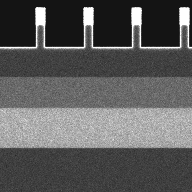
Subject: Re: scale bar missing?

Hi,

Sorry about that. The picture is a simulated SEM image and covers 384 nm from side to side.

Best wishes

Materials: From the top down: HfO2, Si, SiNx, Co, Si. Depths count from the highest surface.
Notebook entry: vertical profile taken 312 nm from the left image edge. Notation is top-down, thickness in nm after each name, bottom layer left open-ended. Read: empty 78, Si 60, SiNx 62, Co 80, Si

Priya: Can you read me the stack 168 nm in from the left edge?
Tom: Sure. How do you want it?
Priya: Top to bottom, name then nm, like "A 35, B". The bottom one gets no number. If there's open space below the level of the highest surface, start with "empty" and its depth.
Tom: HfO2 34, Si 104, SiNx 62, Co 80, Si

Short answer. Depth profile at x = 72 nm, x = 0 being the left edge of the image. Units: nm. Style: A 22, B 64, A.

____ HfO2 34, Si 104, SiNx 62, Co 80, Si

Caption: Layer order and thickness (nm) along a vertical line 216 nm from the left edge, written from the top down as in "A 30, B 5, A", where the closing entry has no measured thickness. empty 78, Si 60, SiNx 62, Co 80, Si